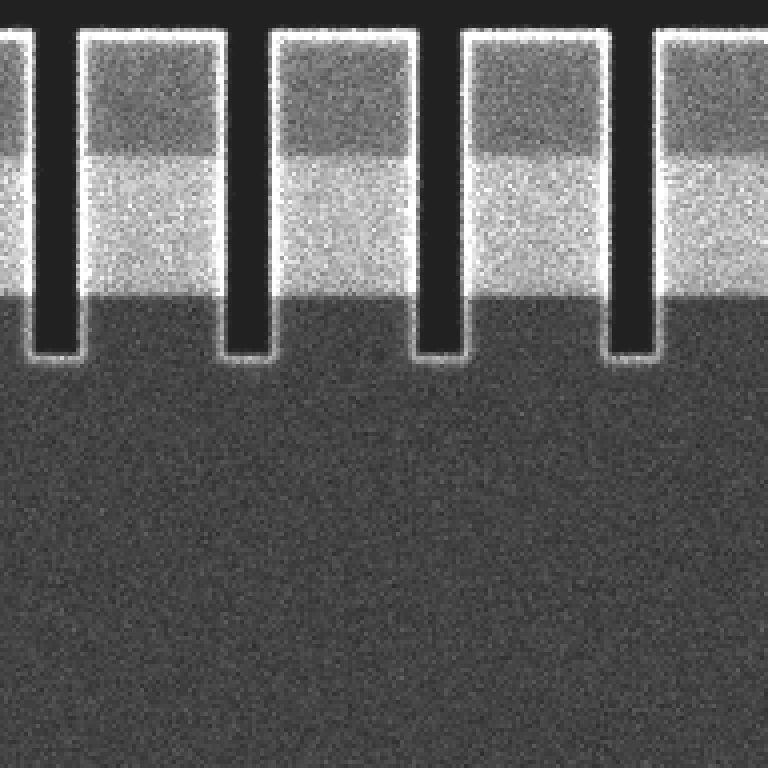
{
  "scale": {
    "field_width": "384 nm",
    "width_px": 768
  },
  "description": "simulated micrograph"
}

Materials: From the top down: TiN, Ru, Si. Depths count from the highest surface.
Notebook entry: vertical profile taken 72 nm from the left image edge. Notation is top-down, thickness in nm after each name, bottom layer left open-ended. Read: TiN 62, Ru 70, Si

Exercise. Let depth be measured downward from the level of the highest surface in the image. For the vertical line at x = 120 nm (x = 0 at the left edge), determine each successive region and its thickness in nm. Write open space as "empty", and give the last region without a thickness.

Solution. empty 162, Si